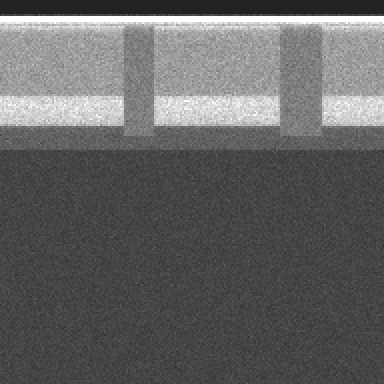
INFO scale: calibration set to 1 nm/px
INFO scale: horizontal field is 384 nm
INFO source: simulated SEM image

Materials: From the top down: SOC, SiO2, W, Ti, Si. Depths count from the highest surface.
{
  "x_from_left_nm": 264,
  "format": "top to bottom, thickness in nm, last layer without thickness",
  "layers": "SOC 10, SiO2 70, W 30, Ti 24, Si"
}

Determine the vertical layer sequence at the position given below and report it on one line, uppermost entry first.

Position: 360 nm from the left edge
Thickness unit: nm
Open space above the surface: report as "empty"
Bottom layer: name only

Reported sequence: SOC 10, SiO2 70, W 30, Ti 24, Si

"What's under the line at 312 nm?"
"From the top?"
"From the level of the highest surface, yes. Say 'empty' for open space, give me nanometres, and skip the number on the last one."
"SOC 120, Ti 14, Si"